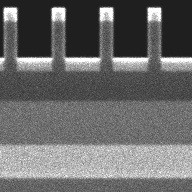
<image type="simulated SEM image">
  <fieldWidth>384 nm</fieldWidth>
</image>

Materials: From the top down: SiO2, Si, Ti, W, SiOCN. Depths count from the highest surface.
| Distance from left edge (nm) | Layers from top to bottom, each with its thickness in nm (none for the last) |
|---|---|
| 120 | SiO2 26, Si 160, Ti 88, W 66, SiOCN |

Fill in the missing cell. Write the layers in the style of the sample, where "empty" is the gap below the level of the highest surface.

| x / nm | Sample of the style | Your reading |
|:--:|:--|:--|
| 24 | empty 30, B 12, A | SiO2 26, Si 160, Ti 88, W 66, SiOCN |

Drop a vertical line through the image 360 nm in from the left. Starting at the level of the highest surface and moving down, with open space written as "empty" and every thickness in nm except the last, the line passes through empty 100, SiO2 26, Si 60, Ti 88, W 66, SiOCN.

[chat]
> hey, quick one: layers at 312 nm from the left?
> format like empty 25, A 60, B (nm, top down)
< SiO2 26, Si 160, Ti 88, W 66, SiOCN